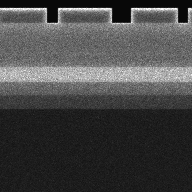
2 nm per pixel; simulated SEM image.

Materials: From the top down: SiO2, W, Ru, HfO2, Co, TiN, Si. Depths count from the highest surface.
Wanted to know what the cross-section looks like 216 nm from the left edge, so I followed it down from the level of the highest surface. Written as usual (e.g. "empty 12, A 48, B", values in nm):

SiO2 30, W 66, Ru 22, HfO2 30, Co 26, TiN 28, Si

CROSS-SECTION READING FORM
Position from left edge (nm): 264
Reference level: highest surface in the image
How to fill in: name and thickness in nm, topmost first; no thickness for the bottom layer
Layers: SiO2 30, W 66, Ru 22, HfO2 30, Co 26, TiN 28, Si